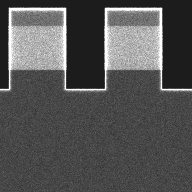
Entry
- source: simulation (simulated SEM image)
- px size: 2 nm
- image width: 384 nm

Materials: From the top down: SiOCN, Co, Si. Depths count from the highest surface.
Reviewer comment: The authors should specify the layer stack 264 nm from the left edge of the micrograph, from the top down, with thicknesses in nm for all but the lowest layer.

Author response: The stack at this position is SiOCN 36, Co 88, Si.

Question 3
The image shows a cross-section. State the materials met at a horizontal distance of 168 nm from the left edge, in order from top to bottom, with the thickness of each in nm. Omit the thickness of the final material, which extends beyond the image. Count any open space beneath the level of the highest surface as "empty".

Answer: empty 162, Si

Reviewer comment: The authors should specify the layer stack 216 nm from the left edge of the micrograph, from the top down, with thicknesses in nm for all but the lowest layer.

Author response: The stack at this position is SiOCN 36, Co 88, Si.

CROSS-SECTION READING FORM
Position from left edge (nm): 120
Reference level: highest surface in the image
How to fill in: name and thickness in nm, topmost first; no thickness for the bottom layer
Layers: SiOCN 36, Co 88, Si